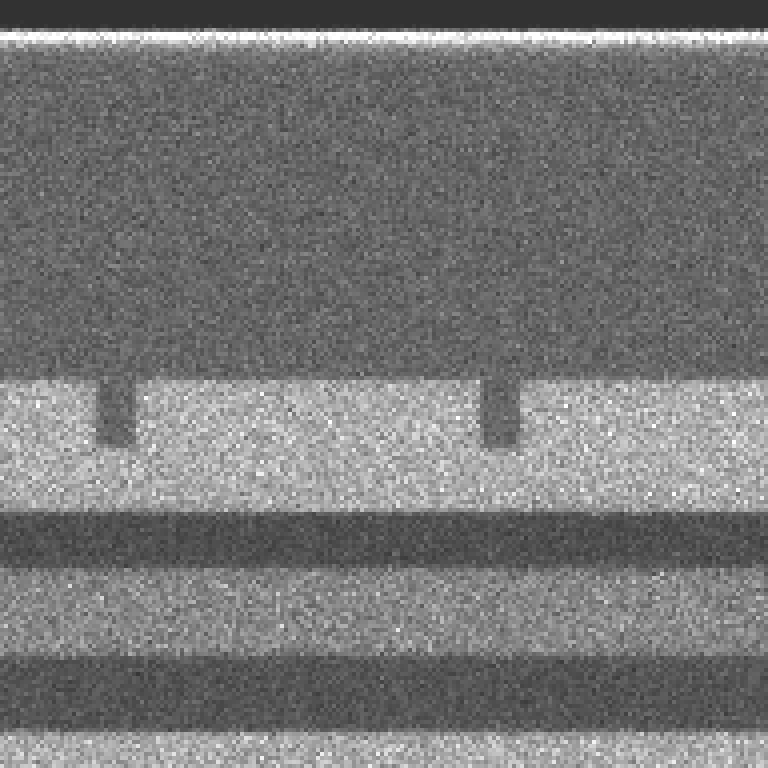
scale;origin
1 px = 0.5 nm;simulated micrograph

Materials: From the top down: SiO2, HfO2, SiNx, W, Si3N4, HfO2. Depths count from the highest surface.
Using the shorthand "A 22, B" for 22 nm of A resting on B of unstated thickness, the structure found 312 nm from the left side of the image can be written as SiO2 174, HfO2 66, SiNx 28, W 44, Si3N4 38, HfO2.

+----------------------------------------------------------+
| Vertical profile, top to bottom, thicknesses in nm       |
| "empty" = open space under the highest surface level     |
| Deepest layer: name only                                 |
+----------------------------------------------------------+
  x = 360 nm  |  SiO2 174, HfO2 66, SiNx 28, W 44, Si3N4 38, HfO2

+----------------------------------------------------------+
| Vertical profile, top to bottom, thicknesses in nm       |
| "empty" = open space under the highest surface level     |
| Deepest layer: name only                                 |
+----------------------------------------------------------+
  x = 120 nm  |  SiO2 174, HfO2 66, SiNx 28, W 44, Si3N4 38, HfO2